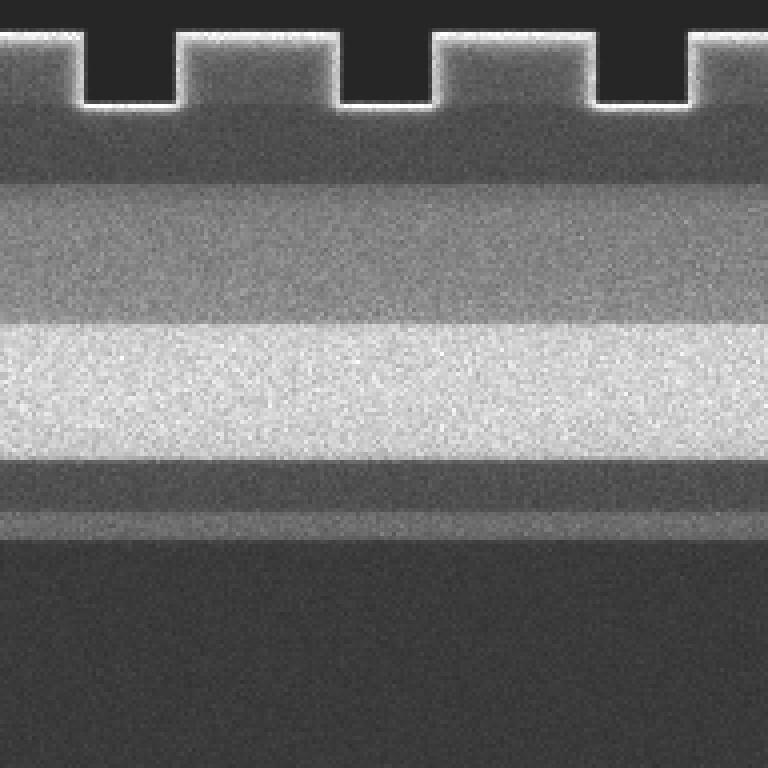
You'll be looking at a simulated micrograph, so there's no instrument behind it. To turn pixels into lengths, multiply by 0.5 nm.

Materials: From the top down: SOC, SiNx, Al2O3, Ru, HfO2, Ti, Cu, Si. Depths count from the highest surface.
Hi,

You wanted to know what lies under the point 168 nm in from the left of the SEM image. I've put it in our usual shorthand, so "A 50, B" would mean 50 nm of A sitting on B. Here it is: SOC 36, SiNx 40, Al2O3 8, Ru 62, HfO2 68, Ti 26, Cu 14, Si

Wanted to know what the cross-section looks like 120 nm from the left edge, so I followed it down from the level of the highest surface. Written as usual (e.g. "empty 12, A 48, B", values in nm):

SOC 36, SiNx 40, Al2O3 8, Ru 62, HfO2 68, Ti 26, Cu 14, Si